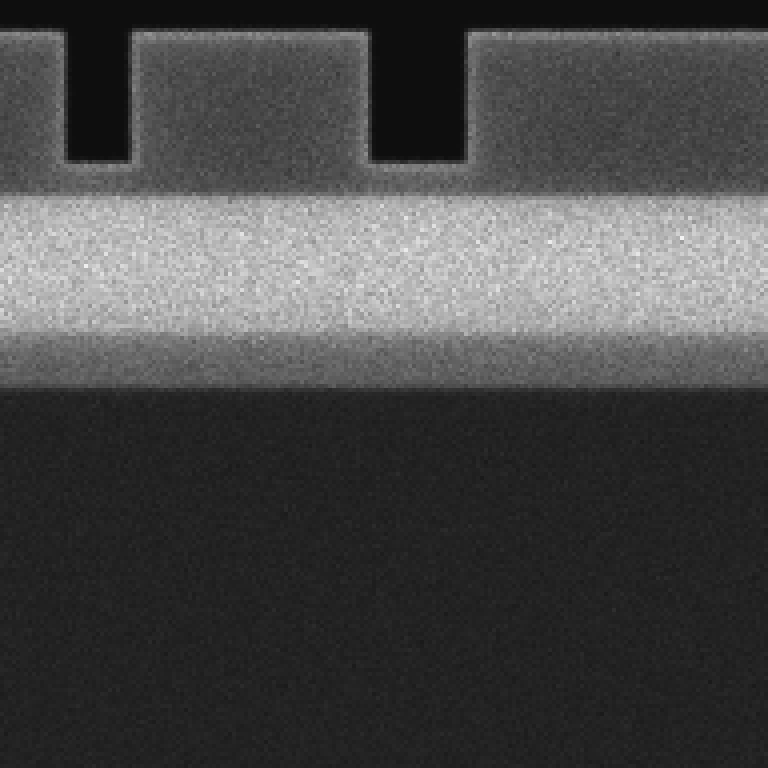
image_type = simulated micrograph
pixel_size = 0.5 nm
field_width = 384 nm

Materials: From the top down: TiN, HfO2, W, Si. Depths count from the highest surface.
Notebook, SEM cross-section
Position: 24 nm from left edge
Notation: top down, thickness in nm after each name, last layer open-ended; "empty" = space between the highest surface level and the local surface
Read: TiN 82, HfO2 68, W 28, Si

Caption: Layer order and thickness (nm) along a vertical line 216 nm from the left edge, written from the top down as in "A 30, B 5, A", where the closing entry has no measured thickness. empty 66, TiN 16, HfO2 68, W 28, Si